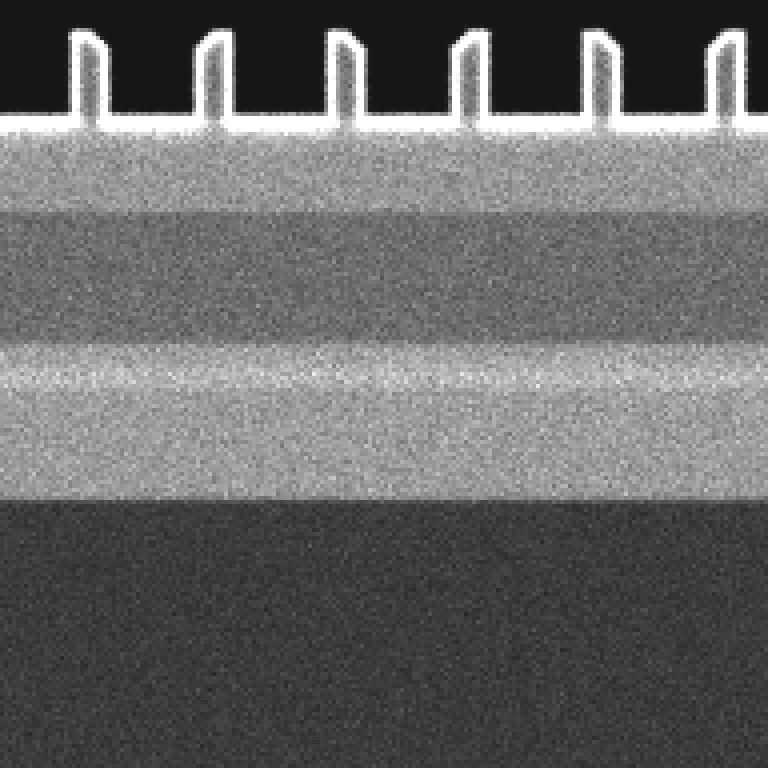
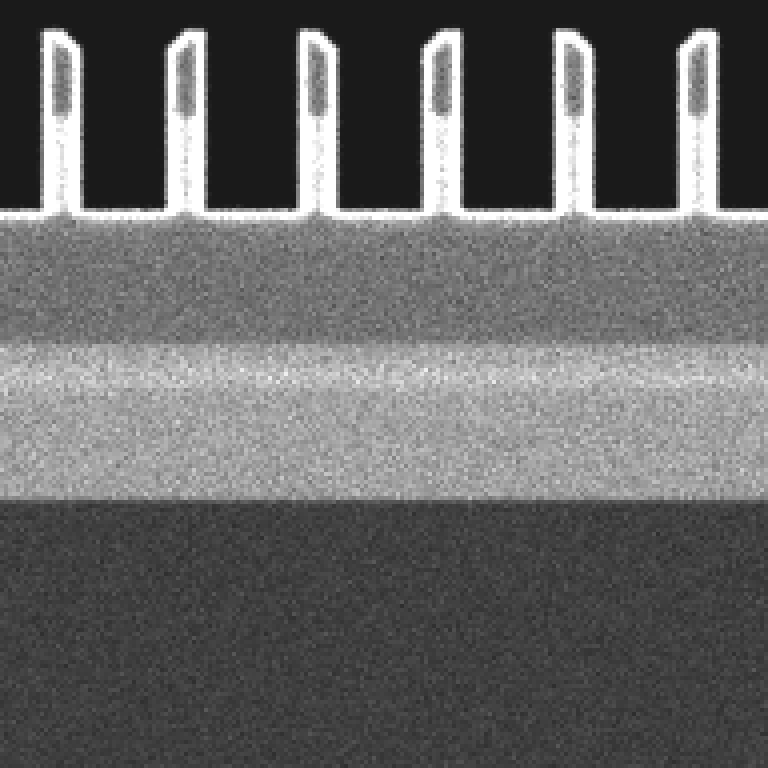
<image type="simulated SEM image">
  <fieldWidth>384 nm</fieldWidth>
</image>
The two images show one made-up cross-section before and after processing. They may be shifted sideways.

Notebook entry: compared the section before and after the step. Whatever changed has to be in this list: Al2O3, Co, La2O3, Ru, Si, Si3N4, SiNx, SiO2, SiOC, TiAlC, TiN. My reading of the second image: SiO2 removed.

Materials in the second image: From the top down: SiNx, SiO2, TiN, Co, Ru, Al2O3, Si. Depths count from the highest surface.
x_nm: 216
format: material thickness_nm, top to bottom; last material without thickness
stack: empty 4, SiNx 38, SiO2 48, TiN 66, Co 12, Ru 10, Al2O3 56, Si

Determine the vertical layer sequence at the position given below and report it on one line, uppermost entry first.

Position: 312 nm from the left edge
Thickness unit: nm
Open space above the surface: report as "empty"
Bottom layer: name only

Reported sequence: empty 90, TiN 66, Co 12, Ru 10, Al2O3 56, Si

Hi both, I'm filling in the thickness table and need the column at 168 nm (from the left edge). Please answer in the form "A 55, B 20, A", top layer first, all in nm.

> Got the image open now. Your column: empty 90, TiN 66, Co 12, Ru 10, Al2O3 56, Si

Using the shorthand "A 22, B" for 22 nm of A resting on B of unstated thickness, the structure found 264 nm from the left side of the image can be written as empty 90, TiN 66, Co 12, Ru 10, Al2O3 56, Si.